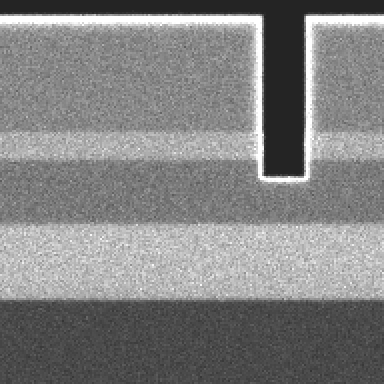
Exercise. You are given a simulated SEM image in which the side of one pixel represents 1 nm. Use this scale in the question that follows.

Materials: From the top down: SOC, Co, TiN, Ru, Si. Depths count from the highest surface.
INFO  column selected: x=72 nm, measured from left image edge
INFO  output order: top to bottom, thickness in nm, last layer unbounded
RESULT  SOC 116, Co 28, TiN 64, Ru 76, Si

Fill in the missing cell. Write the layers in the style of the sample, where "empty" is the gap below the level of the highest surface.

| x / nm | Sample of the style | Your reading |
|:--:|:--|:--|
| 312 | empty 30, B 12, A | SOC 116, Co 28, TiN 64, Ru 76, Si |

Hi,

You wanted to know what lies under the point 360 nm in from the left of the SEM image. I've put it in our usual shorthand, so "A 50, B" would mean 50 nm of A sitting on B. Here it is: SOC 116, Co 28, TiN 64, Ru 76, Si